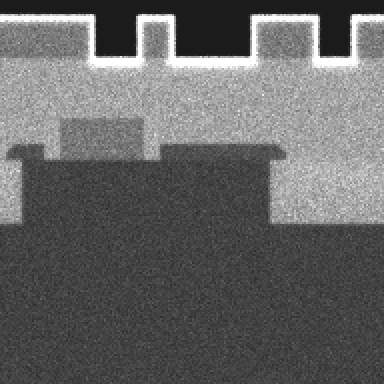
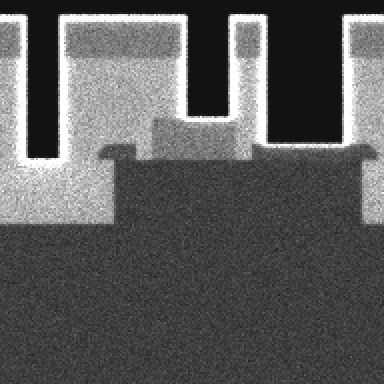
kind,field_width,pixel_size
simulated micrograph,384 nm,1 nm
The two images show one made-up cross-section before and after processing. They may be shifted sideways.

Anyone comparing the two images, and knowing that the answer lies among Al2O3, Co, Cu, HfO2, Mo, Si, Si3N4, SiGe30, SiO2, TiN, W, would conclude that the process removed SiO2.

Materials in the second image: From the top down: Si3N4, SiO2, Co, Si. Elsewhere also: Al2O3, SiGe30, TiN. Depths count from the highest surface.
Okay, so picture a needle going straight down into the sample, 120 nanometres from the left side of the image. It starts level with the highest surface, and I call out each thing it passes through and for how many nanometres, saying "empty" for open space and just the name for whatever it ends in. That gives Si3N4 42, SiO2 86, SiGe30 16, Si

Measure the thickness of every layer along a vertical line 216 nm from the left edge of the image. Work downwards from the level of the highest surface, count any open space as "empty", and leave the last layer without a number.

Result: empty 102, TiN 42, Si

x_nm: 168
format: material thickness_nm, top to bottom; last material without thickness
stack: Si3N4 42, SiO2 60, TiN 42, Si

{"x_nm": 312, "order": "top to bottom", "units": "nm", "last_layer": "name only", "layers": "empty 128, SiGe30 16, Si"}